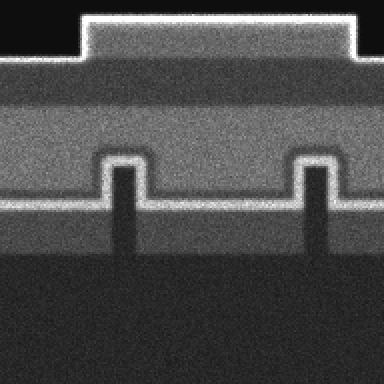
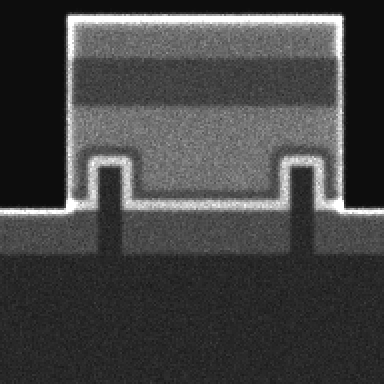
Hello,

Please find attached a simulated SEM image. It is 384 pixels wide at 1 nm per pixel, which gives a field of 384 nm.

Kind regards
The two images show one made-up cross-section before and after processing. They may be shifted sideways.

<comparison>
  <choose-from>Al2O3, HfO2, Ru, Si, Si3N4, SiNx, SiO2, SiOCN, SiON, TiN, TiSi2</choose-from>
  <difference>HfO2 and Ru and SiNx and TiN removed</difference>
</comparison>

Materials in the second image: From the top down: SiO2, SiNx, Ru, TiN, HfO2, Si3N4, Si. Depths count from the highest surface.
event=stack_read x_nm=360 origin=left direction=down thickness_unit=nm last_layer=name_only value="empty 194, Si3N4 44, Si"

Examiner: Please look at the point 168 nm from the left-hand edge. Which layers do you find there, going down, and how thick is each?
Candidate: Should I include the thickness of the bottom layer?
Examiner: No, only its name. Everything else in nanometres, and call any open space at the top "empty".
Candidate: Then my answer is SiO2 42, SiNx 48, Ru 84, TiN 10, HfO2 10, Si3N4 44, Si